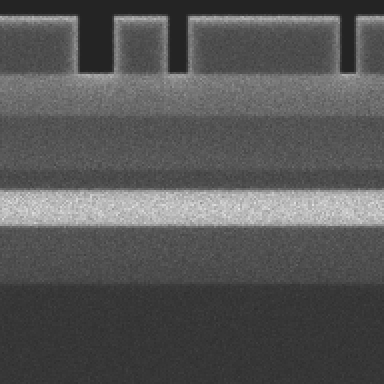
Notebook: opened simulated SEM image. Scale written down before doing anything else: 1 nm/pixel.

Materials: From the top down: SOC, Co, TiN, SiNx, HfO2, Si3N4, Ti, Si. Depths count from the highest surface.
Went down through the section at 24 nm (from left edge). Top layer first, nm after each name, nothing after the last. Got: SOC 58, Co 42, TiN 54, SiNx 20, HfO2 36, Si3N4 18, Ti 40, Si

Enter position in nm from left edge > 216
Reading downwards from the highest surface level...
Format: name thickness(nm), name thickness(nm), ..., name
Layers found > SOC 58, Co 42, TiN 54, SiNx 20, HfO2 36, Si3N4 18, Ti 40, Si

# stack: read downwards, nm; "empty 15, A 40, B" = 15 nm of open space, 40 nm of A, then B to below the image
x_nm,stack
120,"SOC 58, Co 42, TiN 54, SiNx 20, HfO2 36, Si3N4 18, Ti 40, Si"